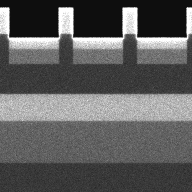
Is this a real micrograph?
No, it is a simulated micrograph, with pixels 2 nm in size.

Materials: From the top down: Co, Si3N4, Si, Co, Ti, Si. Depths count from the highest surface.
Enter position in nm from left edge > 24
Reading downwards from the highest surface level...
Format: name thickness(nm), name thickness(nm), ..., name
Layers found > empty 60, Co 22, Si3N4 30, Si 60, Co 54, Ti 84, Si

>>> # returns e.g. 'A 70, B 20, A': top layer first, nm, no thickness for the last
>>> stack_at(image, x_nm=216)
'empty 60, Co 22, Si3N4 30, Si 60, Co 54, Ti 84, Si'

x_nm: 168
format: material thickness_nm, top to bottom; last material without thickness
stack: empty 60, Co 22, Si3N4 30, Si 60, Co 54, Ti 84, Si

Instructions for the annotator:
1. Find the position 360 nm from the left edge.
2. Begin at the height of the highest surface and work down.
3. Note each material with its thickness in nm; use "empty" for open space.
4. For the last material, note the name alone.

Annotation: empty 60, Co 22, Si3N4 30, Si 60, Co 54, Ti 84, Si